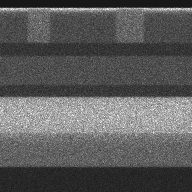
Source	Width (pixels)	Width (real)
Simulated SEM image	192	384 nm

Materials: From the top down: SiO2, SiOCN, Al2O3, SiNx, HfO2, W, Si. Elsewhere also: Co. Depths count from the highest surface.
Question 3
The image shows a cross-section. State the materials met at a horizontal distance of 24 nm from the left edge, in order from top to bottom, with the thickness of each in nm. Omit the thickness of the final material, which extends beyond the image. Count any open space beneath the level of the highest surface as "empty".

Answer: SiO2 70, SiOCN 26, Al2O3 58, SiNx 24, HfO2 72, W 68, Si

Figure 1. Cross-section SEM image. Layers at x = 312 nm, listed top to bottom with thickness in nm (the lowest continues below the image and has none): SiO2 70, SiOCN 26, Al2O3 58, SiNx 24, HfO2 72, W 68, Si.